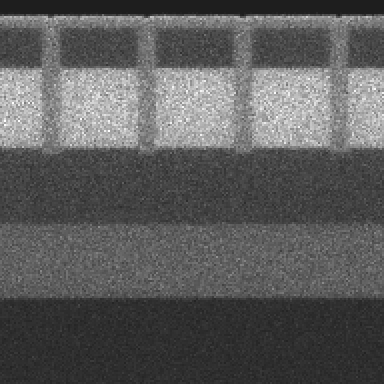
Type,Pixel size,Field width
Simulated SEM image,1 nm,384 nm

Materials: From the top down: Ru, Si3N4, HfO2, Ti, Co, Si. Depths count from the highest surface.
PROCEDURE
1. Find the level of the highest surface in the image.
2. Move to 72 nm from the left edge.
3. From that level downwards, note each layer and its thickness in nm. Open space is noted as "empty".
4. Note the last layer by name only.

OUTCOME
Ru 12, Si3N4 40, HfO2 80, Ti 76, Co 74, Si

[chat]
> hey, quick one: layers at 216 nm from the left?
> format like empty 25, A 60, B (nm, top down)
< Ru 12, Si3N4 40, HfO2 80, Ti 76, Co 74, Si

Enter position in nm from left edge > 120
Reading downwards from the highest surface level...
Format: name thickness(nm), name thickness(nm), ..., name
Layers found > Ru 12, Si3N4 40, HfO2 80, Ti 76, Co 74, Si